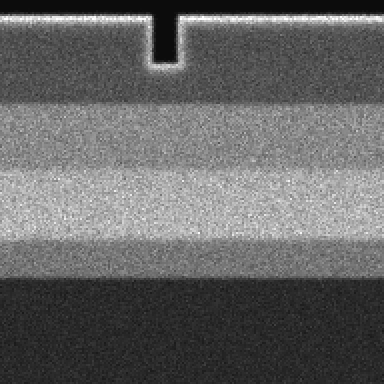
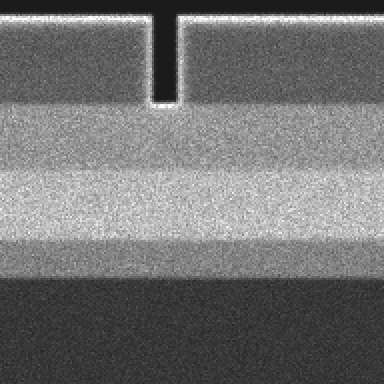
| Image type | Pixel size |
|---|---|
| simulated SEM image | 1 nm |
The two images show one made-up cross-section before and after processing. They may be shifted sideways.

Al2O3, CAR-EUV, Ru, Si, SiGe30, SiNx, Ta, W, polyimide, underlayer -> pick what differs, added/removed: underlayer removed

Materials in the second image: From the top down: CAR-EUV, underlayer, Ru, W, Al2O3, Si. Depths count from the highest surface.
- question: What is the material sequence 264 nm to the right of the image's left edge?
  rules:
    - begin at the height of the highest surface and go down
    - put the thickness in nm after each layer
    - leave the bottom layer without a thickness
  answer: CAR-EUV 48, underlayer 40, Ru 66, W 70, Al2O3 38, Si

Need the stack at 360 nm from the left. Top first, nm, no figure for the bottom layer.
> CAR-EUV 48, underlayer 40, Ru 66, W 70, Al2O3 38, Si